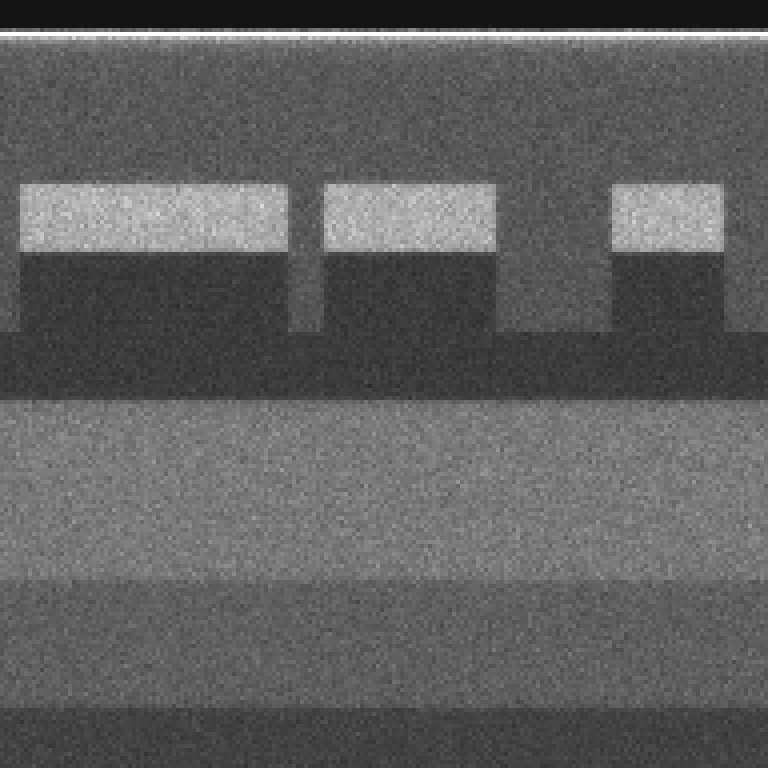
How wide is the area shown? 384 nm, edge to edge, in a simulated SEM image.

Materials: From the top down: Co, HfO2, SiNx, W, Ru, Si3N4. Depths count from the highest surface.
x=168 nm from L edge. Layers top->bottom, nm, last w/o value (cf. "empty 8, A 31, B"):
Co 76, HfO2 34, SiNx 74, W 90, Ru 64, Si3N4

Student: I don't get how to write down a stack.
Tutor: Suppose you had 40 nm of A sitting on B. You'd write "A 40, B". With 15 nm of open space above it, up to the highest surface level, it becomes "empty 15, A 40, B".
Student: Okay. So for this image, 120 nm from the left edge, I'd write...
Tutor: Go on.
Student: Co 76, HfO2 34, SiNx 74, W 90, Ru 64, Si3N4